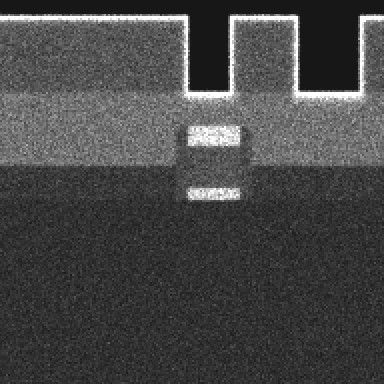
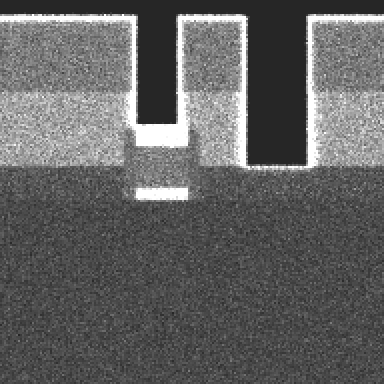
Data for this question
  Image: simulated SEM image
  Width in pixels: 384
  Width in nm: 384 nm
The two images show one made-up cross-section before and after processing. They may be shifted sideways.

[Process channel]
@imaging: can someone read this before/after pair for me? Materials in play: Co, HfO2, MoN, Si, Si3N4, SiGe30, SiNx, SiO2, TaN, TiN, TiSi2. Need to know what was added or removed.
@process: SiO2 removed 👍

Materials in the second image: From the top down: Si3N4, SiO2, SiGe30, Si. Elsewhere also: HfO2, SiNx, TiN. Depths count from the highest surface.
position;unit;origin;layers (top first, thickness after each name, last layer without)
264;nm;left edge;empty 150, SiGe30 34, Si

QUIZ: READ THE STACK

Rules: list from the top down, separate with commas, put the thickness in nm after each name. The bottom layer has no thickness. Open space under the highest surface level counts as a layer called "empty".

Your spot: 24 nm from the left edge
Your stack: Si3N4 76, SiO2 74, SiGe30 34, Si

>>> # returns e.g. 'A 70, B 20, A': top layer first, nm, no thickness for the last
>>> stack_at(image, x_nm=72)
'Si3N4 76, SiO2 74, SiGe30 34, Si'